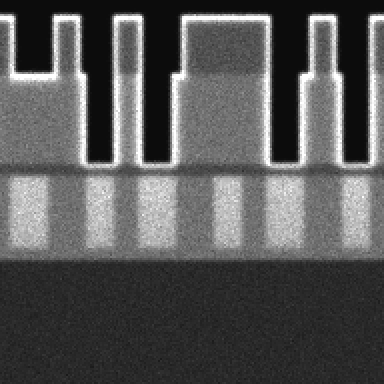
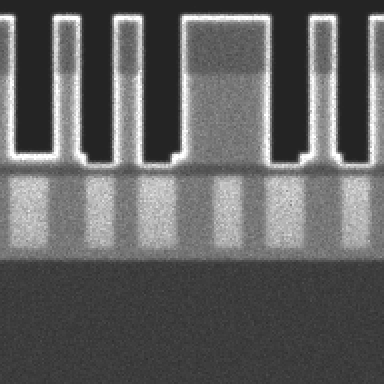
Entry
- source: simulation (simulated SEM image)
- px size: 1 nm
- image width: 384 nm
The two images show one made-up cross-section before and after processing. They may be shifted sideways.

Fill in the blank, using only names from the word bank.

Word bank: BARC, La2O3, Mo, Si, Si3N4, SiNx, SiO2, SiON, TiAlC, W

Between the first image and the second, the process removed SiO2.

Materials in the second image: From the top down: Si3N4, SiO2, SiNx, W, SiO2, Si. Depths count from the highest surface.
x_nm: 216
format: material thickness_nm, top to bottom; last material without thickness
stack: Si3N4 58, SiO2 90, SiNx 12, W 72, SiO2 12, Si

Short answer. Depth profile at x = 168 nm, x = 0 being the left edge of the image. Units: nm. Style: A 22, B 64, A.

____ empty 148, SiNx 12, W 72, SiO2 12, Si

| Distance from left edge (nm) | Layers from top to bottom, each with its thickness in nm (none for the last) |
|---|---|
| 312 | Si3N4 58, SiO2 90, SiNx 12, SiO2 84, Si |